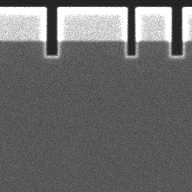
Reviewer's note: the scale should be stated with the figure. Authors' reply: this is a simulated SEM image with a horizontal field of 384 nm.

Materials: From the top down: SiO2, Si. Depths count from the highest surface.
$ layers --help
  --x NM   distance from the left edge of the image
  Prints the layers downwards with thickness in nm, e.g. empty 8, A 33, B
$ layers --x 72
SiO2 66, Si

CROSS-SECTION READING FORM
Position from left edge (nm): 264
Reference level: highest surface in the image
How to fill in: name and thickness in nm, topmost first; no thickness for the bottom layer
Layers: empty 96, Si